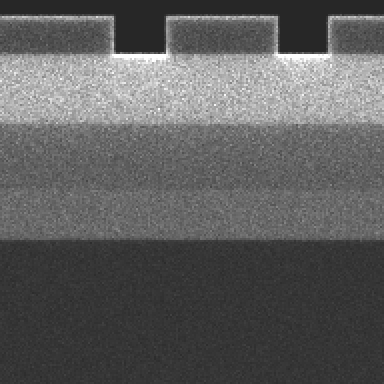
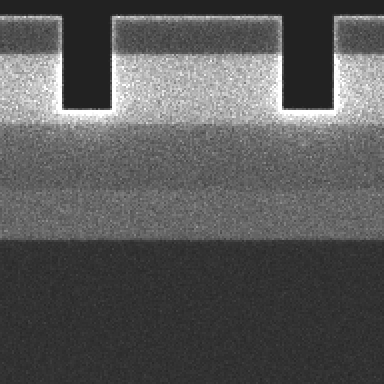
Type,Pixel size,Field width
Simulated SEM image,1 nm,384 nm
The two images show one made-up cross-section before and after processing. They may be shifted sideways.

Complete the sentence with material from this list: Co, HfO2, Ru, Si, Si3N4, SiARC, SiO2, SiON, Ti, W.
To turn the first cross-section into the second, HfO2 must be removed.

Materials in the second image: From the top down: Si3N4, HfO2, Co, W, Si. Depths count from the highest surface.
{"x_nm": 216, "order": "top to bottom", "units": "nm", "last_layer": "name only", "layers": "Si3N4 38, HfO2 70, Co 66, W 50, Si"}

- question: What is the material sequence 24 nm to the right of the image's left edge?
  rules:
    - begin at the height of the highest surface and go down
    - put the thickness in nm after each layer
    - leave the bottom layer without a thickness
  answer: Si3N4 38, HfO2 70, Co 66, W 50, Si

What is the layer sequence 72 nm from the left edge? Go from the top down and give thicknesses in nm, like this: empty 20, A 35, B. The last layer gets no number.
empty 94, HfO2 14, Co 66, W 50, Si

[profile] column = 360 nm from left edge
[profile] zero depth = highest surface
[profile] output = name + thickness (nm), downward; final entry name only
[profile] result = Si3N4 38, HfO2 70, Co 66, W 50, Si